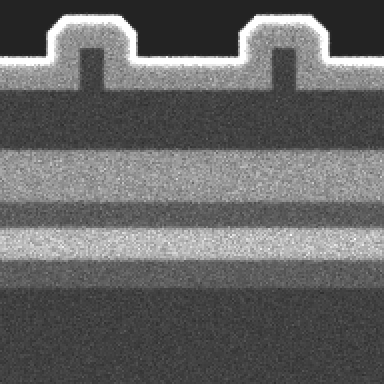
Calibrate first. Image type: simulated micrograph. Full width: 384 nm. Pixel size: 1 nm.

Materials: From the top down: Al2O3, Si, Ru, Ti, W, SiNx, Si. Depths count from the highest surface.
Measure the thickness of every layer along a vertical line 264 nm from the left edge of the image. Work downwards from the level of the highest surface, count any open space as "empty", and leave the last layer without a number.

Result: Al2O3 74, Si 60, Ru 52, Ti 26, W 32, SiNx 28, Si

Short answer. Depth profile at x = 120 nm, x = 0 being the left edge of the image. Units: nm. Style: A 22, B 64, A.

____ empty 2, Al2O3 72, Si 60, Ru 52, Ti 26, W 32, SiNx 28, Si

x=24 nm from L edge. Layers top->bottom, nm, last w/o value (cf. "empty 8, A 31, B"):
empty 42, Al2O3 32, Si 60, Ru 52, Ti 26, W 32, SiNx 28, Si